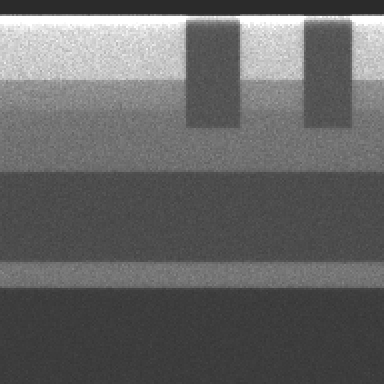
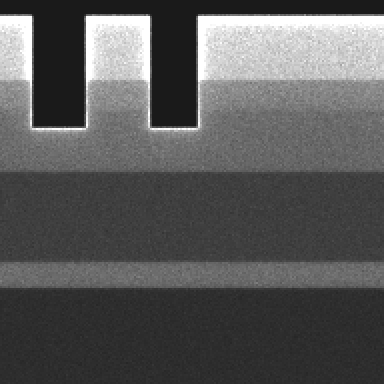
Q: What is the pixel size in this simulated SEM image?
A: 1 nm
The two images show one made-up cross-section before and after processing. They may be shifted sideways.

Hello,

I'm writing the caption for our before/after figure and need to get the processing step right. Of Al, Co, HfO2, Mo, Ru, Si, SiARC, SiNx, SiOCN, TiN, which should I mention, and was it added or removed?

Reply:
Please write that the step removed SiARC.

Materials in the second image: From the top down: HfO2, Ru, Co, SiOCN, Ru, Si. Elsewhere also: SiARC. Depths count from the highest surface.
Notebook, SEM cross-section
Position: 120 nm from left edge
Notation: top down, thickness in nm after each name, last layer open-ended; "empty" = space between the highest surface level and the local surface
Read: HfO2 64, Ru 30, Co 62, SiOCN 90, Ru 26, Si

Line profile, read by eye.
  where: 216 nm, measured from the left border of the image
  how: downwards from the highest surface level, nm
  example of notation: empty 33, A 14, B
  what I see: HfO2 64, Ru 30, Co 62, SiOCN 90, Ru 26, Si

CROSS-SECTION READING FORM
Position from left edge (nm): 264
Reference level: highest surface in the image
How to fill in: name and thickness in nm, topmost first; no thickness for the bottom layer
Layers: HfO2 64, Ru 30, Co 62, SiOCN 90, Ru 26, Si